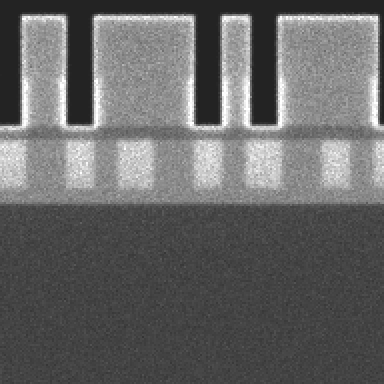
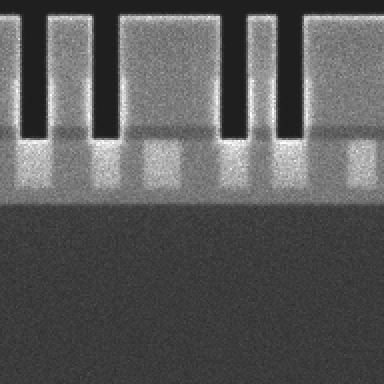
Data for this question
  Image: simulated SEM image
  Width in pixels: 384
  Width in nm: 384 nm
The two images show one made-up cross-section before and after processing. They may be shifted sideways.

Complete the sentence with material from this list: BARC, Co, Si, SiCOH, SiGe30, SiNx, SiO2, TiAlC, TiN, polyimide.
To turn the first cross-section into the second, SiNx must be removed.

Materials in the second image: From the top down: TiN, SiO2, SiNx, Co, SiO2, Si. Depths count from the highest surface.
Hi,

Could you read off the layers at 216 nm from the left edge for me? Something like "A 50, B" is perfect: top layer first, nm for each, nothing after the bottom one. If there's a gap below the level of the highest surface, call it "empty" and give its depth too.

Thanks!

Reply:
TiN 62, SiO2 48, SiNx 14, SiO2 64, Si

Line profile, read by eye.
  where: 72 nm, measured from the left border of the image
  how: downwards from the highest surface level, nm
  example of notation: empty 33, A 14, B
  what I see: TiN 62, SiO2 48, SiNx 14, SiO2 64, Si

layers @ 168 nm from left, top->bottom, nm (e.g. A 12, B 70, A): TiN 62, SiO2 48, SiNx 14, Co 48, SiO2 16, Si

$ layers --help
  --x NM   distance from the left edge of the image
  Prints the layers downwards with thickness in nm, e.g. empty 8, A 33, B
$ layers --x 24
empty 124, Co 48, SiO2 16, Si